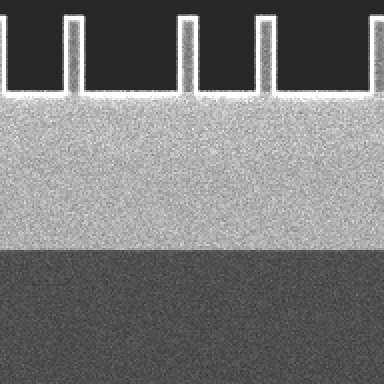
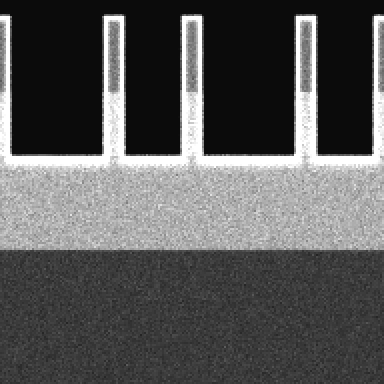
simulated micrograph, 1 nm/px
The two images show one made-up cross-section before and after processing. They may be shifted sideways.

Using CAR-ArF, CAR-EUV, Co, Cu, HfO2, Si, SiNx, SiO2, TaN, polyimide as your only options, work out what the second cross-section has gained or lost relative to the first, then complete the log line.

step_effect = removed Co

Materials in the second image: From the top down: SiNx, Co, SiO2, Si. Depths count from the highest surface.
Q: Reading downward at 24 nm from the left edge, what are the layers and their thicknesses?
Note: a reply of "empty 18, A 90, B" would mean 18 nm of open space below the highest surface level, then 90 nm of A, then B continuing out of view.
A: empty 140, SiO2 94, Si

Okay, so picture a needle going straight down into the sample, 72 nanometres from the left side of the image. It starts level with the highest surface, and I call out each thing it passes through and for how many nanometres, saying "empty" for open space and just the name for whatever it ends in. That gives empty 140, SiO2 94, Si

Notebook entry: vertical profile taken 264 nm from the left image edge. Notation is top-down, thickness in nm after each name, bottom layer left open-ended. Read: empty 140, SiO2 94, Si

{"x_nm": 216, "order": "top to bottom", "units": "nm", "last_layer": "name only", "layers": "empty 140, SiO2 94, Si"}